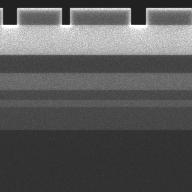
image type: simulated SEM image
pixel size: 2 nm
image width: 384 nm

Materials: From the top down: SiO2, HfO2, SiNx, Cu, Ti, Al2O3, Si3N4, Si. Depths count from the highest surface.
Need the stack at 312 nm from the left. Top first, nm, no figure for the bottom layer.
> SiO2 34, HfO2 60, SiNx 36, Cu 34, Ti 20, Al2O3 14, Si3N4 46, Si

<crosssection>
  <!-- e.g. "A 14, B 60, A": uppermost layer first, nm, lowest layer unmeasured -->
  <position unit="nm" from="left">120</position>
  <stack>SiO2 34, HfO2 60, SiNx 36, Cu 34, Ti 20, Al2O3 14, Si3N4 46, Si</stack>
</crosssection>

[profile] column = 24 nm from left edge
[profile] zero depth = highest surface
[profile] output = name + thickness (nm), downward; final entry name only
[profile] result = empty 34, HfO2 60, SiNx 36, Cu 34, Ti 20, Al2O3 14, Si3N4 46, Si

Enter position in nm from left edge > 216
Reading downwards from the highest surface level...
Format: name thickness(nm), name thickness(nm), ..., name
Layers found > SiO2 34, HfO2 60, SiNx 36, Cu 34, Ti 20, Al2O3 14, Si3N4 46, Si